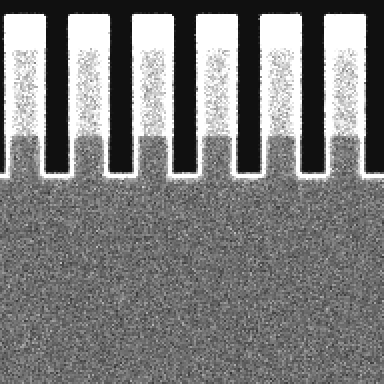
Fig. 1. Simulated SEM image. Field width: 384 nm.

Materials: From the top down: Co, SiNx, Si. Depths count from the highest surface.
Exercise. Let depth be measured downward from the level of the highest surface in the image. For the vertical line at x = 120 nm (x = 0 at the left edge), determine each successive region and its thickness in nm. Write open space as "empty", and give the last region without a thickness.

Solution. empty 158, Si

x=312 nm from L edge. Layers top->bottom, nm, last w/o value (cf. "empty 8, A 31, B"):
empty 158, Si